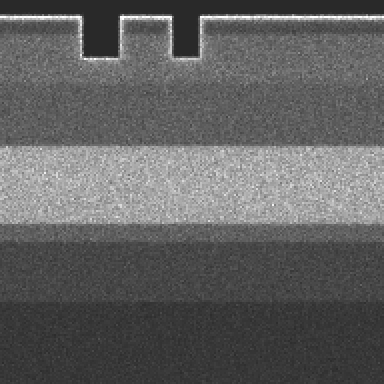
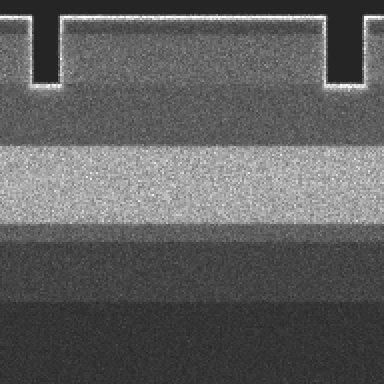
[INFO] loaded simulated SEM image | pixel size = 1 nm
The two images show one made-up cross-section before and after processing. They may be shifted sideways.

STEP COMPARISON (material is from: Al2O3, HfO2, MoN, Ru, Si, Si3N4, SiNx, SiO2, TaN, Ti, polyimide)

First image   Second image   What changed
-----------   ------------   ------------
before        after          Ru, removed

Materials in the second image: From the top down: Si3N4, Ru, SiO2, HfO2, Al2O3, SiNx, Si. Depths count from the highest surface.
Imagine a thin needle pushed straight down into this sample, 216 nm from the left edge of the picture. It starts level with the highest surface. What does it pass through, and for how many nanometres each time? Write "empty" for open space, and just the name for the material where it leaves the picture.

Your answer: Si3N4 18, Ru 50, SiO2 62, HfO2 78, Al2O3 18, SiNx 60, Si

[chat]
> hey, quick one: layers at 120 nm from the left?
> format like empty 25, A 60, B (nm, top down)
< Si3N4 18, Ru 50, SiO2 62, HfO2 78, Al2O3 18, SiNx 60, Si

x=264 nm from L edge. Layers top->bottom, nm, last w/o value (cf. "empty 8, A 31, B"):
Si3N4 18, Ru 50, SiO2 62, HfO2 78, Al2O3 18, SiNx 60, Si